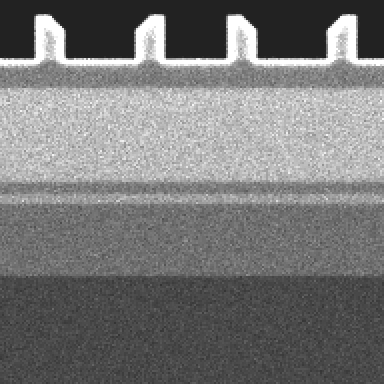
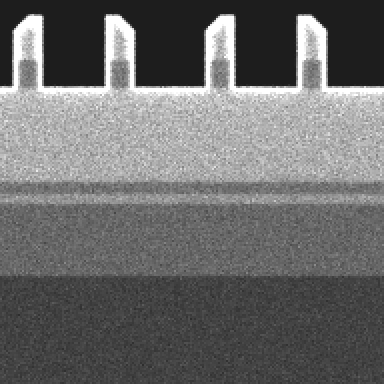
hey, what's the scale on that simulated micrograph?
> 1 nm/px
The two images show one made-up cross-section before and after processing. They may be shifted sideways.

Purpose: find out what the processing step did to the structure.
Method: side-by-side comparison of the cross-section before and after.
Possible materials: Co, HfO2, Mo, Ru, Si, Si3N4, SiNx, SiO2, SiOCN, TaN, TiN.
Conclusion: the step removed Si3N4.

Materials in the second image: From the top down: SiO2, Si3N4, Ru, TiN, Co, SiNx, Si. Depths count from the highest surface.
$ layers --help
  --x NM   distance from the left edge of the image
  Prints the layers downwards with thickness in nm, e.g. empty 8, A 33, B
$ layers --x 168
empty 72, Ru 94, TiN 12, Co 10, SiNx 72, Si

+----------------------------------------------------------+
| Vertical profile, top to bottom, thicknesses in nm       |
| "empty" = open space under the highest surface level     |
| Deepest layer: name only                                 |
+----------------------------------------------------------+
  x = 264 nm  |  empty 72, Ru 94, TiN 12, Co 10, SiNx 72, Si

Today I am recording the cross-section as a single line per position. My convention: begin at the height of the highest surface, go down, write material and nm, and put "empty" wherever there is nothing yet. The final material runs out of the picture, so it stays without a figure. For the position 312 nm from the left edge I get empty 2, SiO2 42, Si3N4 28, Ru 94, TiN 12, Co 10, SiNx 72, Si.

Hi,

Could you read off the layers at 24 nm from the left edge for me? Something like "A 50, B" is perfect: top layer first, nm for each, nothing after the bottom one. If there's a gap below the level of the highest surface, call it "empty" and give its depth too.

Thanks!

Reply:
empty 4, SiO2 40, Si3N4 28, Ru 94, TiN 12, Co 10, SiNx 72, Si